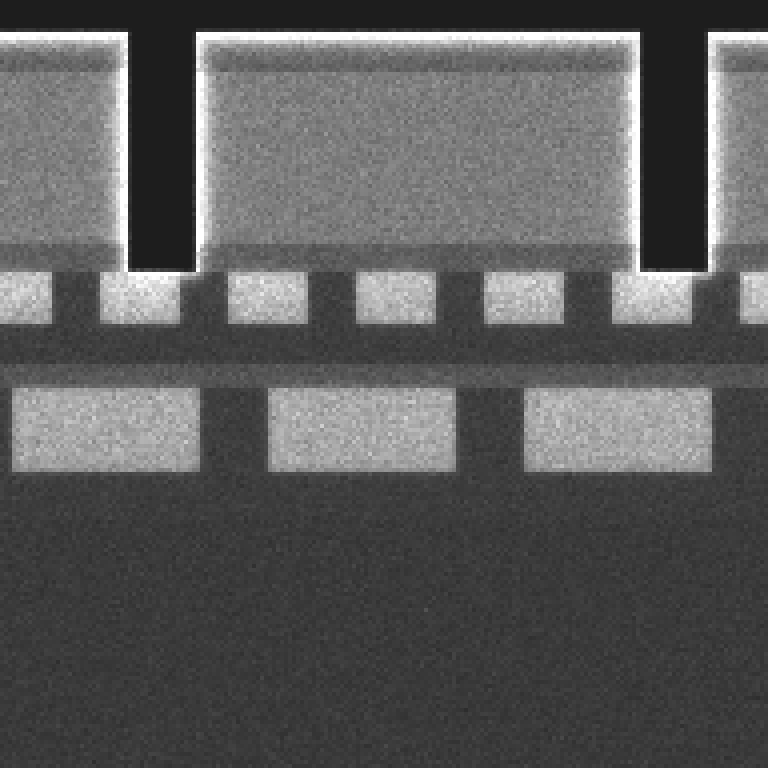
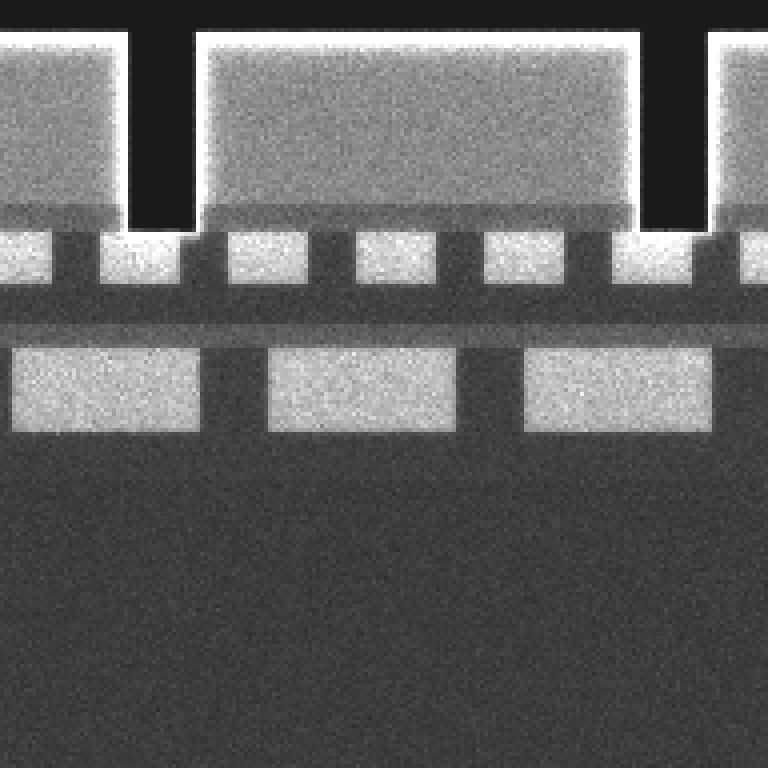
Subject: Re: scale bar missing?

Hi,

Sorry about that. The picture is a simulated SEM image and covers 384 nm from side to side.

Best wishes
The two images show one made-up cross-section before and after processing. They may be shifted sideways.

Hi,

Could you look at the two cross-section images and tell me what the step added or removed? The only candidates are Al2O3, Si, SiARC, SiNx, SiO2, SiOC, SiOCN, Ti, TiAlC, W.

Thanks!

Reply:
removed SiARC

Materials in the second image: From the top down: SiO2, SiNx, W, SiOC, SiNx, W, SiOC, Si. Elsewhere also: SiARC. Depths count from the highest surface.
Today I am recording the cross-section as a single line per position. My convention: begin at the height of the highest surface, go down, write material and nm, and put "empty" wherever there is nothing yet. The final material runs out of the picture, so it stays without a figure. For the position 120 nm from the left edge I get SiO2 86, SiNx 14, W 26, SiOC 20, SiNx 12, SiOC 66, Si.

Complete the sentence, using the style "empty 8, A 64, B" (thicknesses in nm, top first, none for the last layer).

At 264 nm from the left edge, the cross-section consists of SiO2 86, SiNx 14, W 26, SiOC 20, SiNx 12, W 42, SiOC 24, Si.